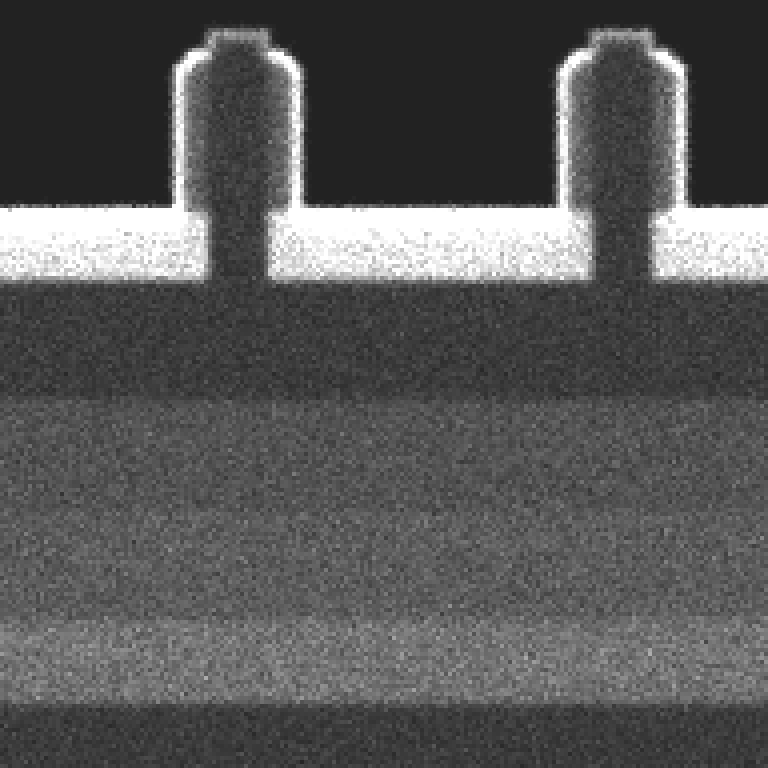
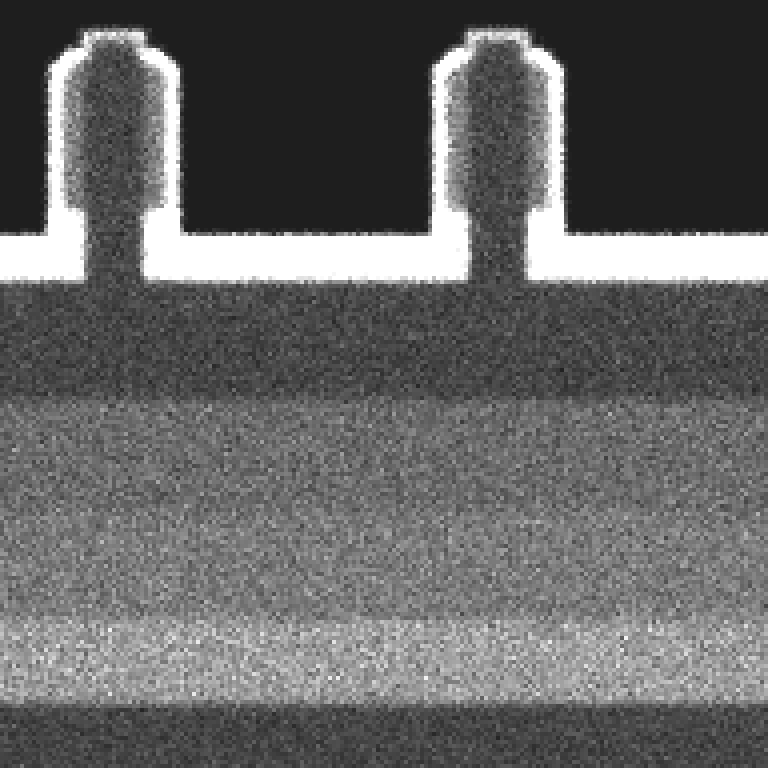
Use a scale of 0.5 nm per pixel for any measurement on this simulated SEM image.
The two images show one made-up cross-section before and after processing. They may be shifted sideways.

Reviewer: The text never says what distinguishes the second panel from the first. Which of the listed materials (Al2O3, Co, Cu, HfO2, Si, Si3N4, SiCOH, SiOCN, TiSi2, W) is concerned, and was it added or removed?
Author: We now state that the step removed HfO2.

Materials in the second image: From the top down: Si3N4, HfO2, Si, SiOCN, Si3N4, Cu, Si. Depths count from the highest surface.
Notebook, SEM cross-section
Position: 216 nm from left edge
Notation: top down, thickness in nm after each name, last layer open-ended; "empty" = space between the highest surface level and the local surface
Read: empty 104, HfO2 20, Si 60, SiOCN 56, Si3N4 54, Cu 42, Si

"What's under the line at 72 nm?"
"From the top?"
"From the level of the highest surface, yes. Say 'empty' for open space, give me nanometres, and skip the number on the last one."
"empty 10, Si3N4 80, HfO2 34, Si 60, SiOCN 56, Si3N4 54, Cu 42, Si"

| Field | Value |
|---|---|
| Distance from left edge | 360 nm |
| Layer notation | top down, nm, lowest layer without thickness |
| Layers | empty 104, HfO2 20, Si 60, SiOCN 56, Si3N4 54, Cu 42, Si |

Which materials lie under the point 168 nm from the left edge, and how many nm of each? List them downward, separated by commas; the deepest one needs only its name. empty 104, HfO2 20, Si 60, SiOCN 56, Si3N4 54, Cu 42, Si